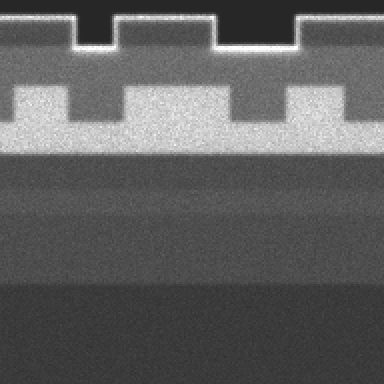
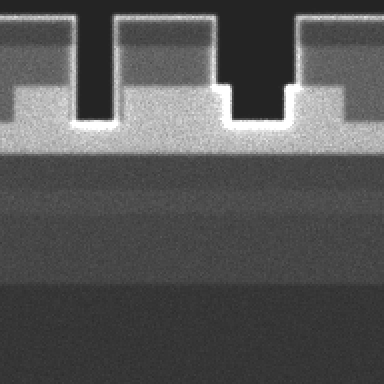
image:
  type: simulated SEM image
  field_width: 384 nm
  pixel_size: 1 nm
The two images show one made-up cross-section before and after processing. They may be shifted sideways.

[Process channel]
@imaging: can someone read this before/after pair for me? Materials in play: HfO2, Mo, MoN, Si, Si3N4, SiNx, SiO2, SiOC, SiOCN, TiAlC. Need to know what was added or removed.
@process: SiO2 removed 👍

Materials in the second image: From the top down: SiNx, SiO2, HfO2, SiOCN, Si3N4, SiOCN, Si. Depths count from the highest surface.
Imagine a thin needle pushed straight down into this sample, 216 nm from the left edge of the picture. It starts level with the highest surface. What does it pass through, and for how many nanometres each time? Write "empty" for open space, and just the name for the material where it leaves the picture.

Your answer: empty 70, HfO2 68, SiOCN 36, Si3N4 24, SiOCN 70, Si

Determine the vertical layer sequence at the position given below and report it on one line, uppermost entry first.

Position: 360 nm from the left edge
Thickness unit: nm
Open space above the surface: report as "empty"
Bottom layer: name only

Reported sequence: SiNx 30, SiO2 76, HfO2 32, SiOCN 36, Si3N4 24, SiOCN 70, Si